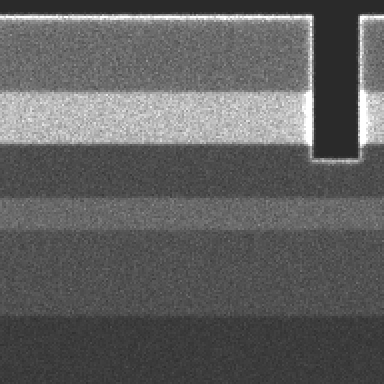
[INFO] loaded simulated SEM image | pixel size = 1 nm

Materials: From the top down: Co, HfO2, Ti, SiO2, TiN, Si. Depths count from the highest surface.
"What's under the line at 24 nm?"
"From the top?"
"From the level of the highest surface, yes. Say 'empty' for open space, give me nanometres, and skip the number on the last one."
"Co 76, HfO2 52, Ti 54, SiO2 32, TiN 86, Si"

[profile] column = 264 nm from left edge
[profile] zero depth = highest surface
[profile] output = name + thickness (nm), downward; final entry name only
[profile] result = Co 76, HfO2 52, Ti 54, SiO2 32, TiN 86, Si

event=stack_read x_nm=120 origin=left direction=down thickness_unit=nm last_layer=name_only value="Co 76, HfO2 52, Ti 54, SiO2 32, TiN 86, Si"